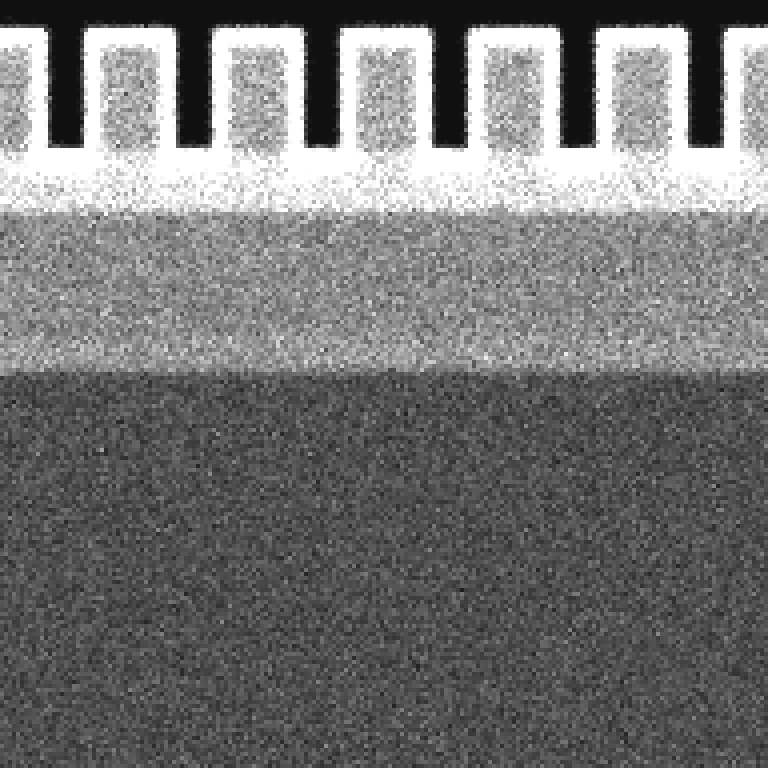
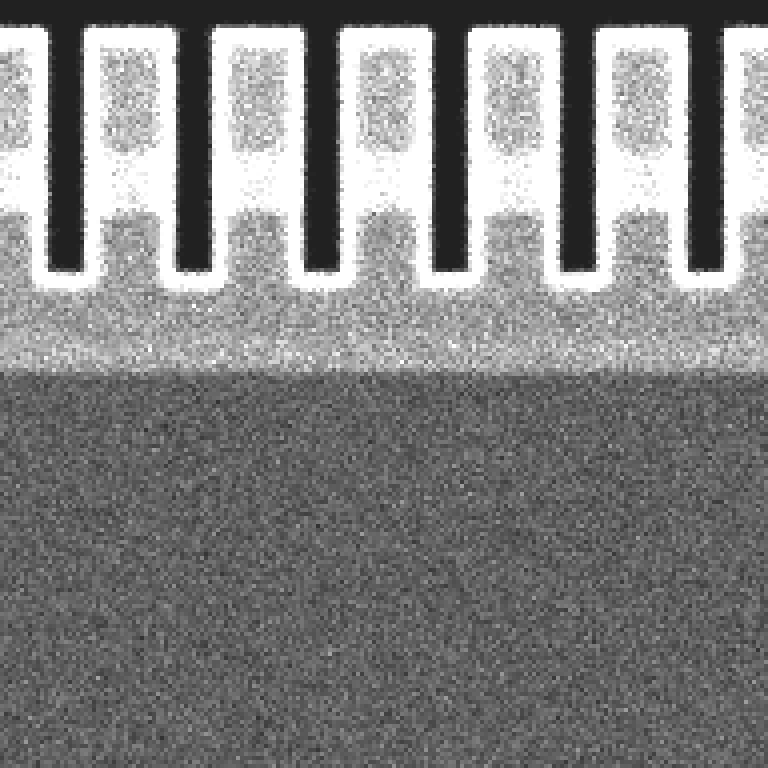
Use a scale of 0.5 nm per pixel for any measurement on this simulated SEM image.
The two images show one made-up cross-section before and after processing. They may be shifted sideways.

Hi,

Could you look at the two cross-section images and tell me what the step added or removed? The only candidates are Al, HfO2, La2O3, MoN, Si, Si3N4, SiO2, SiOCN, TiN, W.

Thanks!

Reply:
removed SiO2 and SiOCN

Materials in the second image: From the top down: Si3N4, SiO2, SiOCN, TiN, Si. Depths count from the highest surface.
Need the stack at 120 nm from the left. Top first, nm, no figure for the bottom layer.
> Si3N4 60, SiO2 30, SiOCN 62, TiN 18, Si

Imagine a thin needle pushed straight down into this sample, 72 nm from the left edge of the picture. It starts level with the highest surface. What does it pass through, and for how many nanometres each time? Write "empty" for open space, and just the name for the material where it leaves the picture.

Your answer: Si3N4 60, SiO2 30, SiOCN 62, TiN 18, Si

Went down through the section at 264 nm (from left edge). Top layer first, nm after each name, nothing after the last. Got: Si3N4 60, SiO2 30, SiOCN 62, TiN 18, Si